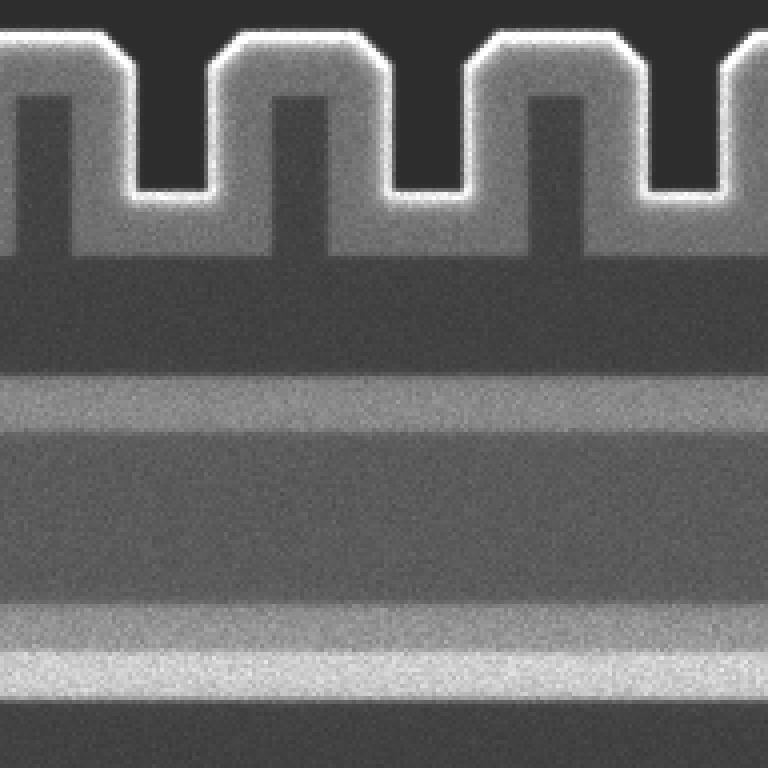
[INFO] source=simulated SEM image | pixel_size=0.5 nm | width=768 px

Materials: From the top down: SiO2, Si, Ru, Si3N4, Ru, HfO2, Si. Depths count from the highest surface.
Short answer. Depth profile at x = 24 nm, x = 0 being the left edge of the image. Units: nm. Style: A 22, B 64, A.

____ SiO2 32, Si 140, Ru 28, Si3N4 86, Ru 24, HfO2 24, Si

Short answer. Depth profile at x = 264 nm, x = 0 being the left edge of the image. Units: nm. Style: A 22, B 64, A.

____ SiO2 32, Si 140, Ru 28, Si3N4 86, Ru 24, HfO2 24, Si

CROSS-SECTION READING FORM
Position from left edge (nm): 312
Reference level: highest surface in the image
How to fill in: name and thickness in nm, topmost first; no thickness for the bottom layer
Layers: empty 6, SiO2 106, Si 60, Ru 28, Si3N4 86, Ru 24, HfO2 24, Si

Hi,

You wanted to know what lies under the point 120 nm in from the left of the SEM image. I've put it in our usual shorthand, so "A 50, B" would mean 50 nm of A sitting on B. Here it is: SiO2 112, Si 60, Ru 28, Si3N4 86, Ru 24, HfO2 24, Si